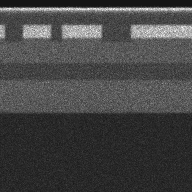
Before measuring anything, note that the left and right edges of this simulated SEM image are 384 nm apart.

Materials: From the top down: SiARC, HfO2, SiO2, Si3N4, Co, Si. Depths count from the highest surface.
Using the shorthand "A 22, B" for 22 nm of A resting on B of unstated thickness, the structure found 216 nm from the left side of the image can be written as SiARC 68, SiO2 42, Si3N4 34, Co 66, Si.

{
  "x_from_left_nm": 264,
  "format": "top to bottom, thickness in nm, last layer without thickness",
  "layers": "SiARC 34, HfO2 26, SiO2 50, Si3N4 34, Co 66, Si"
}